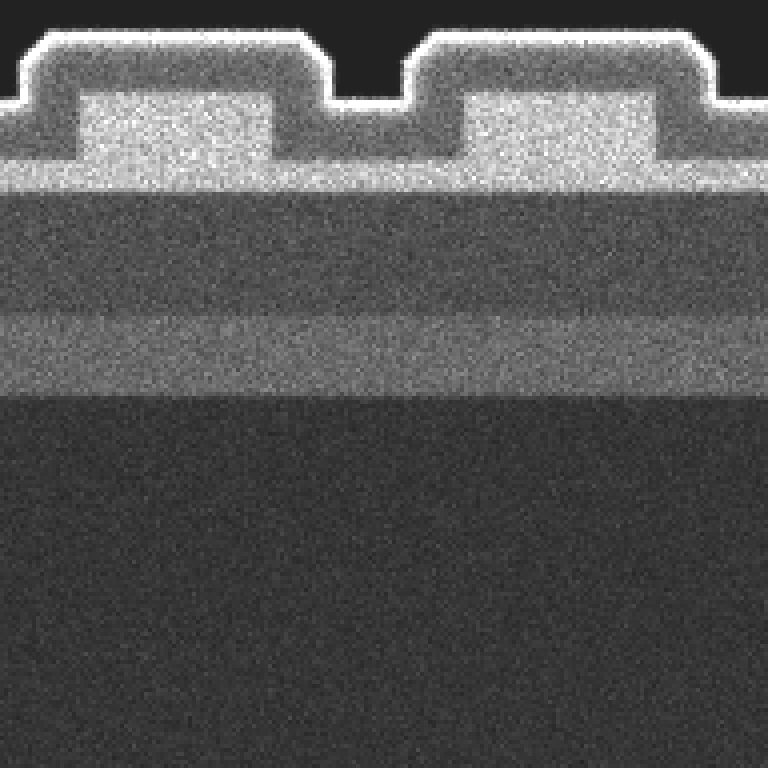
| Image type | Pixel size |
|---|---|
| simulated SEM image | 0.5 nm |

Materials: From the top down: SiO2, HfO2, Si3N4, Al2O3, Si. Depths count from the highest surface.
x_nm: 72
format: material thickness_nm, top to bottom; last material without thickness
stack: SiO2 30, HfO2 50, Si3N4 62, Al2O3 40, Si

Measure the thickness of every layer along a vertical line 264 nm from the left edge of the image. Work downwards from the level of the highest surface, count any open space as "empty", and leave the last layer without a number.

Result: SiO2 30, HfO2 50, Si3N4 62, Al2O3 40, Si